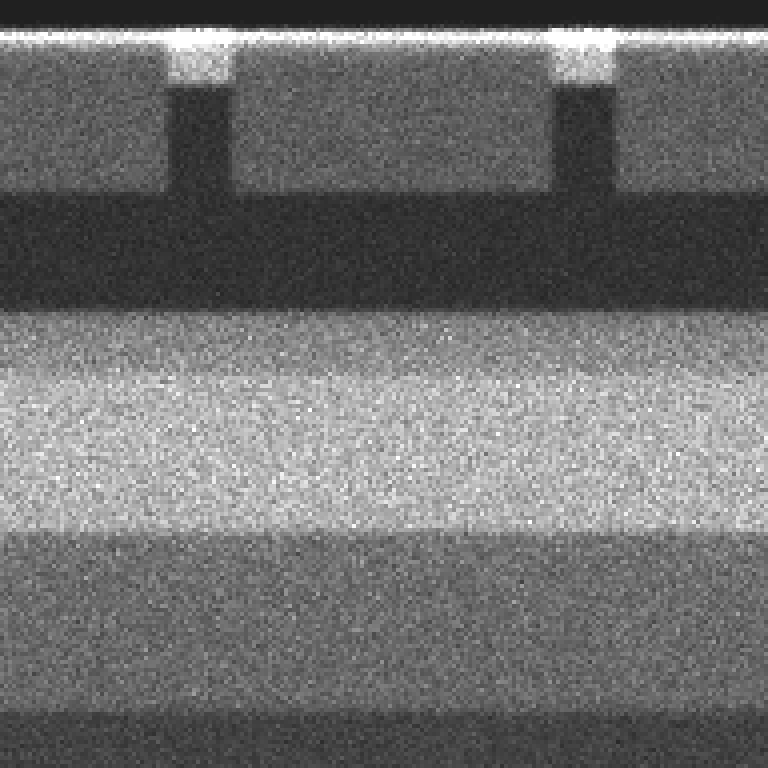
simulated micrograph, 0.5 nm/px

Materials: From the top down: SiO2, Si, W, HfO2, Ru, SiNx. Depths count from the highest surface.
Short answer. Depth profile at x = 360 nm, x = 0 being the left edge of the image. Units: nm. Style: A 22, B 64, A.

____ SiO2 80, Si 60, W 32, HfO2 78, Ru 90, SiNx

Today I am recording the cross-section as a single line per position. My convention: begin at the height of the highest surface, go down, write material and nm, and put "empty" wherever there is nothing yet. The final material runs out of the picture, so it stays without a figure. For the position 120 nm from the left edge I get SiO2 80, Si 60, W 32, HfO2 78, Ru 90, SiNx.